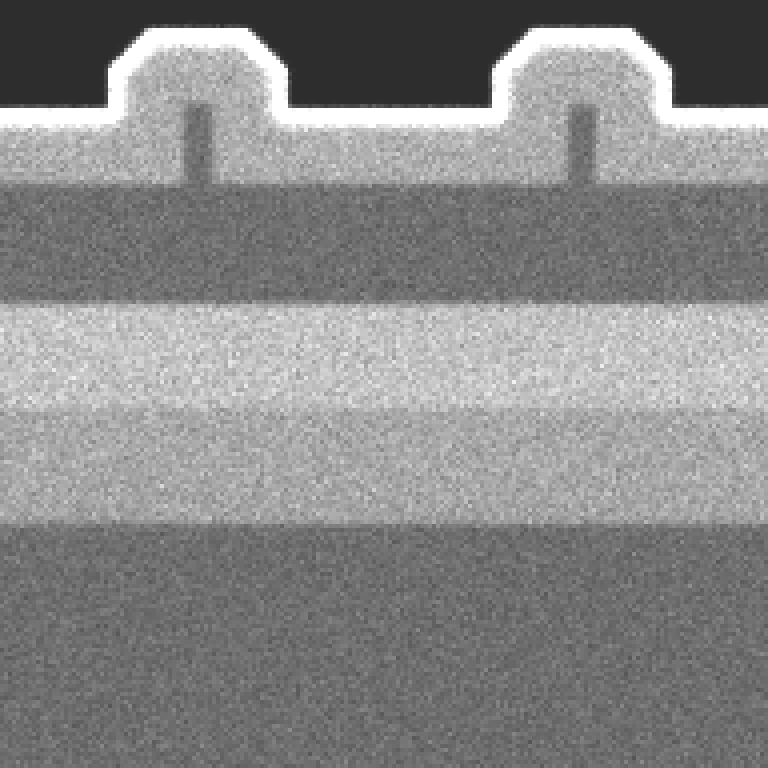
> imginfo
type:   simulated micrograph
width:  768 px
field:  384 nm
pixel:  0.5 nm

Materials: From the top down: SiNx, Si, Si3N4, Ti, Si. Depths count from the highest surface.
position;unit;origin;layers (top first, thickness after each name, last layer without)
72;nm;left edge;empty 2, SiNx 74, Si 60, Si3N4 52, Ti 58, Si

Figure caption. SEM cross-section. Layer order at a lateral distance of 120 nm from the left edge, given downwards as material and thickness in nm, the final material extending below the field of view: SiNx 76, Si 60, Si3N4 52, Ti 58, Si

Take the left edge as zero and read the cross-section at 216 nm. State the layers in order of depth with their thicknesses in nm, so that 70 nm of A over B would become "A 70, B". empty 40, SiNx 36, Si 60, Si3N4 52, Ti 58, Si